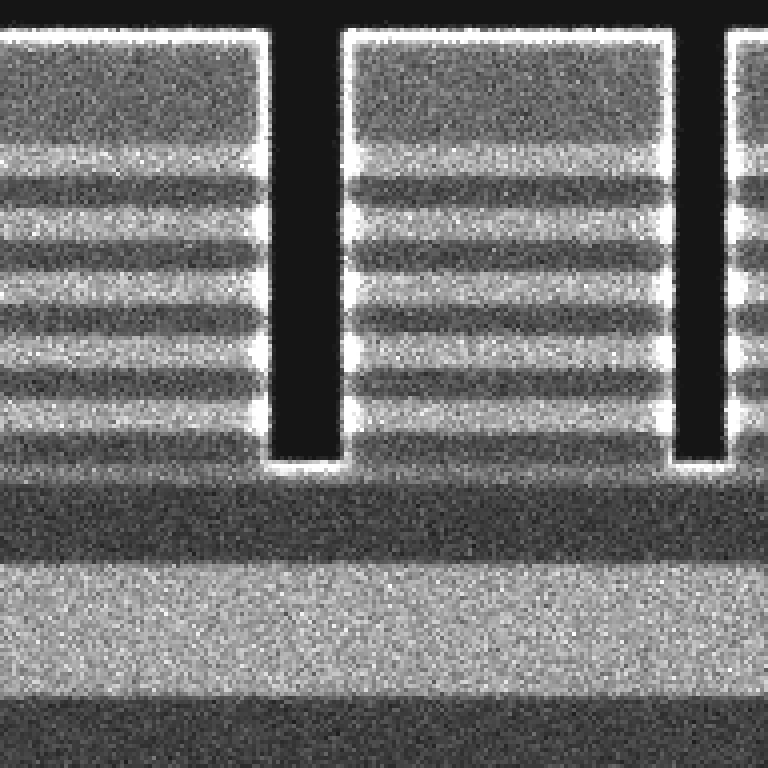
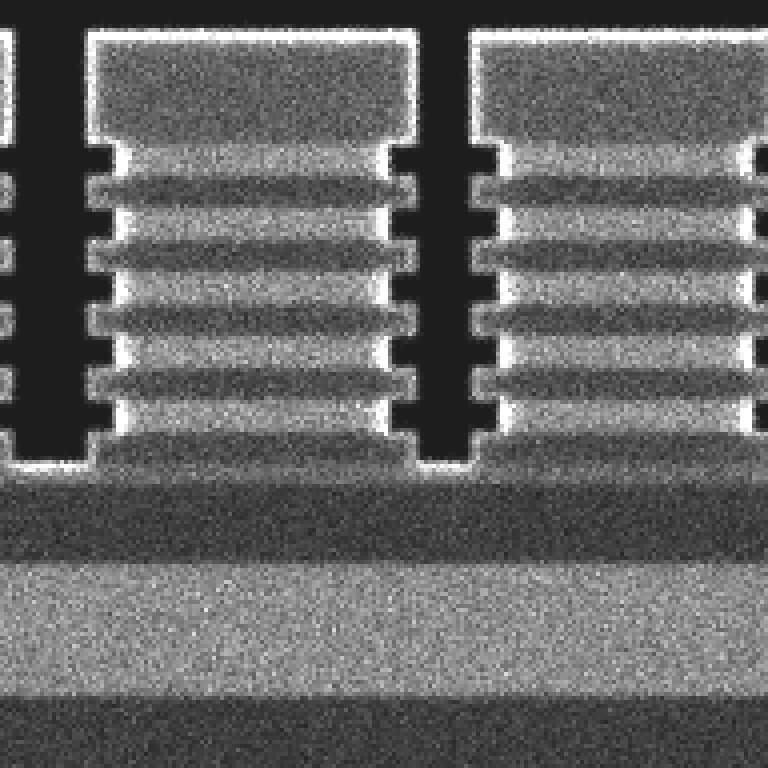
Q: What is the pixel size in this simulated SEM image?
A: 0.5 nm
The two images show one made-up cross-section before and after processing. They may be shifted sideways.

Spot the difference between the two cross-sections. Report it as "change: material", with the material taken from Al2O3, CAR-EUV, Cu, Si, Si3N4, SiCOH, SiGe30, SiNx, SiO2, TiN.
removed: Al2O3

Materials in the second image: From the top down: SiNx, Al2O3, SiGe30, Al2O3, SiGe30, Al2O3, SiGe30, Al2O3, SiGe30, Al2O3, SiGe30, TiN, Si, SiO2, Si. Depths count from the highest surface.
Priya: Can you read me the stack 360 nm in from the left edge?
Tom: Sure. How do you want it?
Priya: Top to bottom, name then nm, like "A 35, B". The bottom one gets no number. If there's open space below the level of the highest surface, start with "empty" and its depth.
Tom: SiNx 56, Al2O3 16, SiGe30 16, Al2O3 16, SiGe30 16, Al2O3 16, SiGe30 16, Al2O3 16, SiGe30 16, Al2O3 16, SiGe30 16, TiN 10, Si 40, SiO2 66, Si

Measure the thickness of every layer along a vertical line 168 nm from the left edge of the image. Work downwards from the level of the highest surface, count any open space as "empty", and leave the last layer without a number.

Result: SiNx 56, Al2O3 16, SiGe30 16, Al2O3 16, SiGe30 16, Al2O3 16, SiGe30 16, Al2O3 16, SiGe30 16, Al2O3 16, SiGe30 16, TiN 10, Si 40, SiO2 66, Si